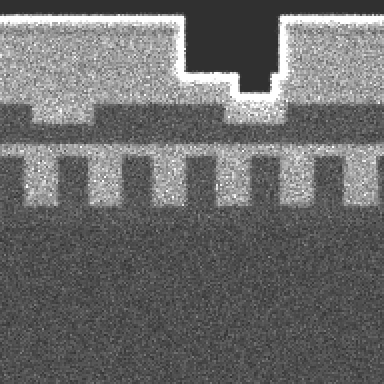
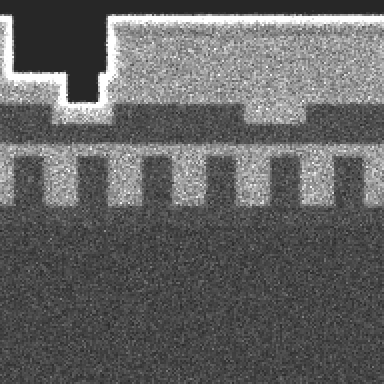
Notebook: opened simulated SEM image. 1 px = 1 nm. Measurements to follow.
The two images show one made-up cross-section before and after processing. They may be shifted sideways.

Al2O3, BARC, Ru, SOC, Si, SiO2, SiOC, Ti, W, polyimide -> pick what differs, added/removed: Al2O3 removed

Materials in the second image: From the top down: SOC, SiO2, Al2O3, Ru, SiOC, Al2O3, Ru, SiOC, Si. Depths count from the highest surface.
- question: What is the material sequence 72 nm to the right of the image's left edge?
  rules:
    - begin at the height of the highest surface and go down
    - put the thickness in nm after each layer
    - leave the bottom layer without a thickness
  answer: empty 88, Ru 20, SiOC 20, Al2O3 12, Ru 50, SiOC 20, Si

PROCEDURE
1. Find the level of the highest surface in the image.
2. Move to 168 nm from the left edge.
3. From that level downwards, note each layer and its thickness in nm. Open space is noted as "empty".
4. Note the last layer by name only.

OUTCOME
SOC 20, SiO2 58, Al2O3 10, SiOC 40, Al2O3 12, SiOC 70, Si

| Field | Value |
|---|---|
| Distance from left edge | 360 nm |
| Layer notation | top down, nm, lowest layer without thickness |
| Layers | SOC 20, SiO2 58, Al2O3 10, SiOC 40, Al2O3 12, SiOC 70, Si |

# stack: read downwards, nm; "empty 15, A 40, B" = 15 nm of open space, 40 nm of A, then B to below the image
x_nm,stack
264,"SOC 20, SiO2 58, Al2O3 10, Ru 20, SiOC 20, Al2O3 12, Ru 50, SiOC 20, Si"